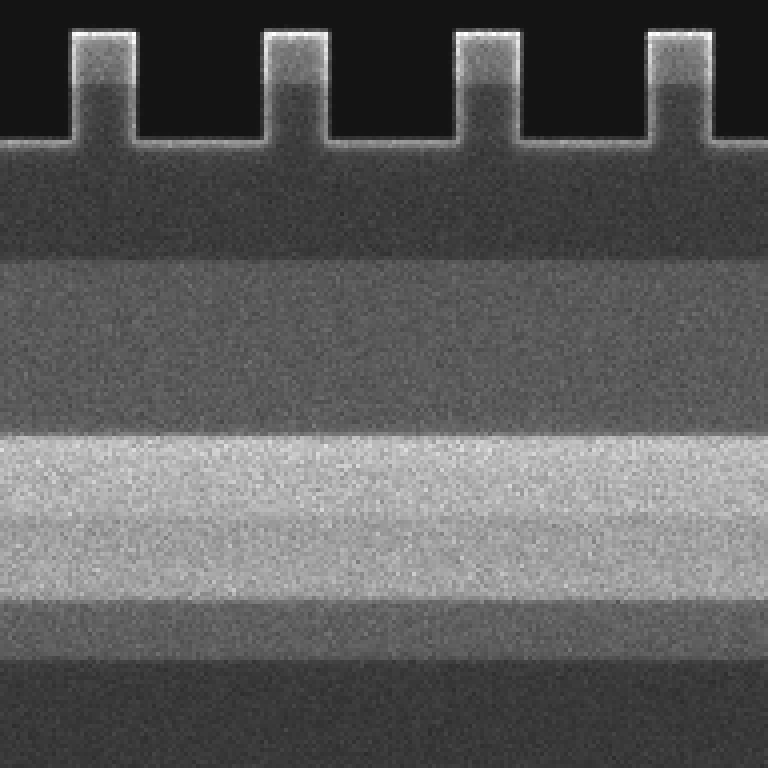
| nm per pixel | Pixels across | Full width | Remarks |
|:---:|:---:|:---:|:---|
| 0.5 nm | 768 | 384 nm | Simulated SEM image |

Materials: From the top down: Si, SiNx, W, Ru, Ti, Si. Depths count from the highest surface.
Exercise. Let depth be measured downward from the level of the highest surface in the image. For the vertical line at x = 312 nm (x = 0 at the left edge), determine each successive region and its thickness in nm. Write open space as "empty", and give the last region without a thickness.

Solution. empty 54, Si 60, SiNx 88, W 40, Ru 42, Ti 30, Si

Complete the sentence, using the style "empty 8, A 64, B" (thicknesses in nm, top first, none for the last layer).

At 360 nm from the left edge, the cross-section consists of empty 54, Si 60, SiNx 88, W 40, Ru 42, Ti 30, Si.